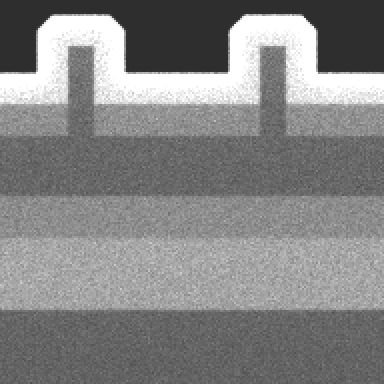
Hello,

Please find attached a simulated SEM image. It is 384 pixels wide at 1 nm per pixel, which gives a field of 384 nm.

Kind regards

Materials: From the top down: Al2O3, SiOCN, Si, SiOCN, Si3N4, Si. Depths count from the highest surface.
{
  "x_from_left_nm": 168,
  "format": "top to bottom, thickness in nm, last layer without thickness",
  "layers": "empty 58, Al2O3 30, SiOCN 32, Si 60, SiOCN 42, Si3N4 72, Si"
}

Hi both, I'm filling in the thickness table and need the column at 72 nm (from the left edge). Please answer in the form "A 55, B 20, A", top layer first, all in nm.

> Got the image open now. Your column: Al2O3 30, Si 150, SiOCN 42, Si3N4 72, Si